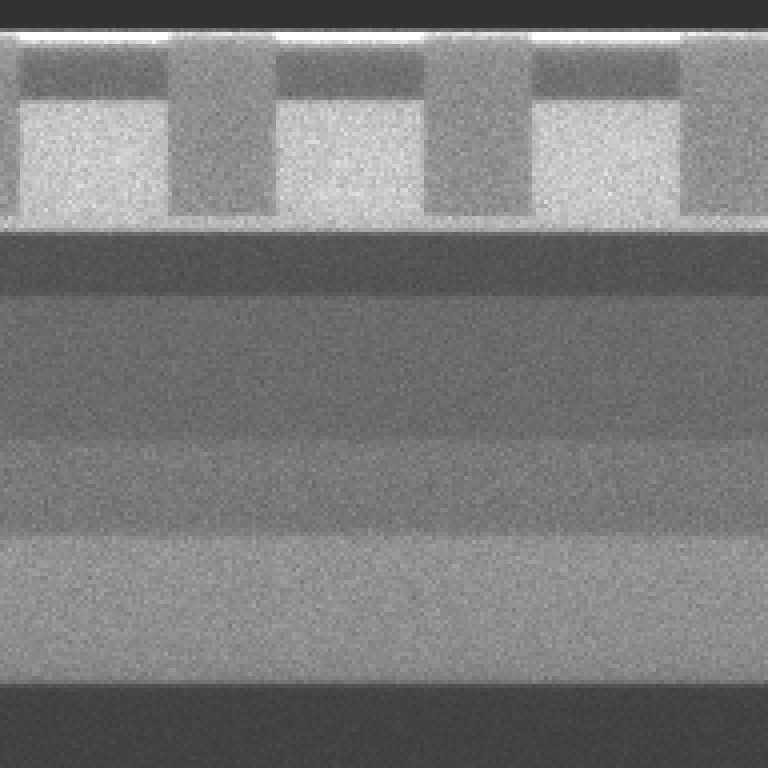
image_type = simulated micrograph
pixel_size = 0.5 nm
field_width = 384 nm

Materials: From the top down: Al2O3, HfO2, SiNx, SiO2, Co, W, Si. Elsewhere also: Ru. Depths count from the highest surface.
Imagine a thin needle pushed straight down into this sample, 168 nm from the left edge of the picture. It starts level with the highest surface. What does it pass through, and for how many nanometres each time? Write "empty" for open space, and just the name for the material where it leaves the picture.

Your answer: Al2O3 34, HfO2 66, SiNx 32, SiO2 72, Co 48, W 74, Si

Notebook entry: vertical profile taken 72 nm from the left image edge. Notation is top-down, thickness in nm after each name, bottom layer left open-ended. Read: Al2O3 34, HfO2 66, SiNx 32, SiO2 72, Co 48, W 74, Si